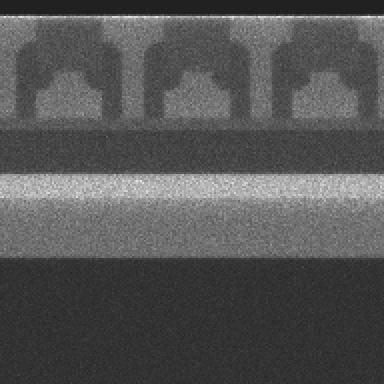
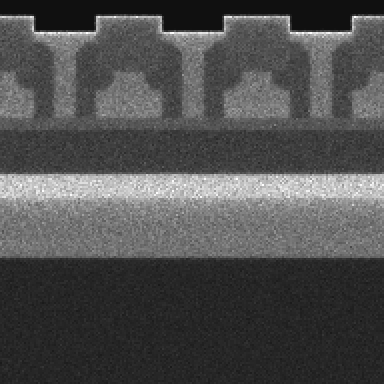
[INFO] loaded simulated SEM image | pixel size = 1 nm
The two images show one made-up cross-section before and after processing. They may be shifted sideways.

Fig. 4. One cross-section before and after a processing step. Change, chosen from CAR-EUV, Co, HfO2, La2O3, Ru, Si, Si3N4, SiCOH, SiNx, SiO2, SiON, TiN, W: Co removed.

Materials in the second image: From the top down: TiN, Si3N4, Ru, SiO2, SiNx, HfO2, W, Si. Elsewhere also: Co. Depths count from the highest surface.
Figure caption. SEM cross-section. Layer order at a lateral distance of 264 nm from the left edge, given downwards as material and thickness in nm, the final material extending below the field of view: TiN 56, Ru 46, SiO2 12, SiNx 44, HfO2 24, W 60, Si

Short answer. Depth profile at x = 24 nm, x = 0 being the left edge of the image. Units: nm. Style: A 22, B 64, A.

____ TiN 56, Si3N4 18, Ru 28, SiO2 12, SiNx 44, HfO2 24, W 60, Si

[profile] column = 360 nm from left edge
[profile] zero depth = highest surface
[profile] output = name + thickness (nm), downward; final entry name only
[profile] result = TiN 56, Si3N4 18, Ru 28, SiO2 12, SiNx 44, HfO2 24, W 60, Si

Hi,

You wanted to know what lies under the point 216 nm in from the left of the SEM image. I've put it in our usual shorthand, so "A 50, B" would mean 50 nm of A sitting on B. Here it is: empty 16, Co 10, Si3N4 76, SiO2 12, SiNx 44, HfO2 24, W 60, Si